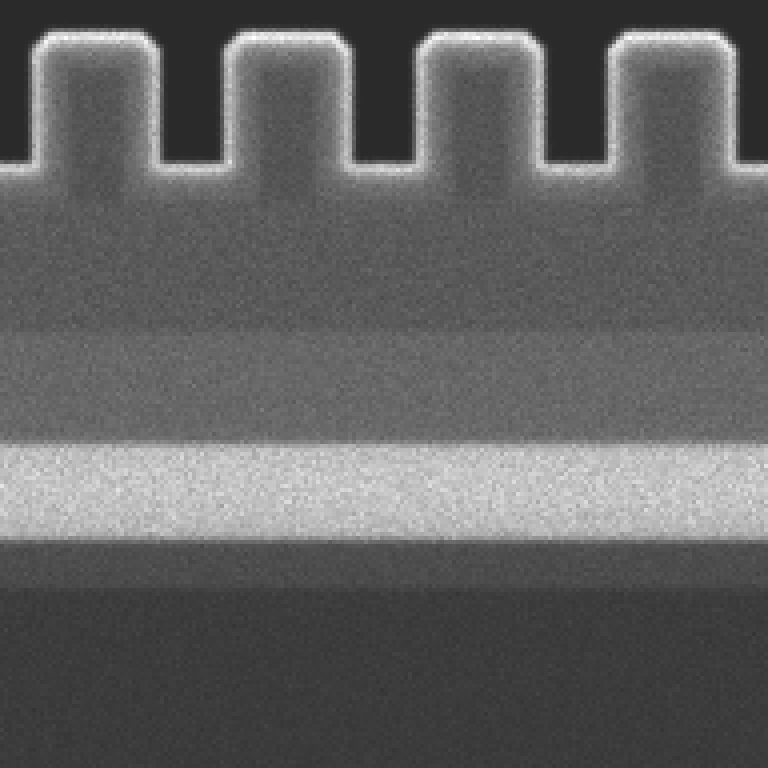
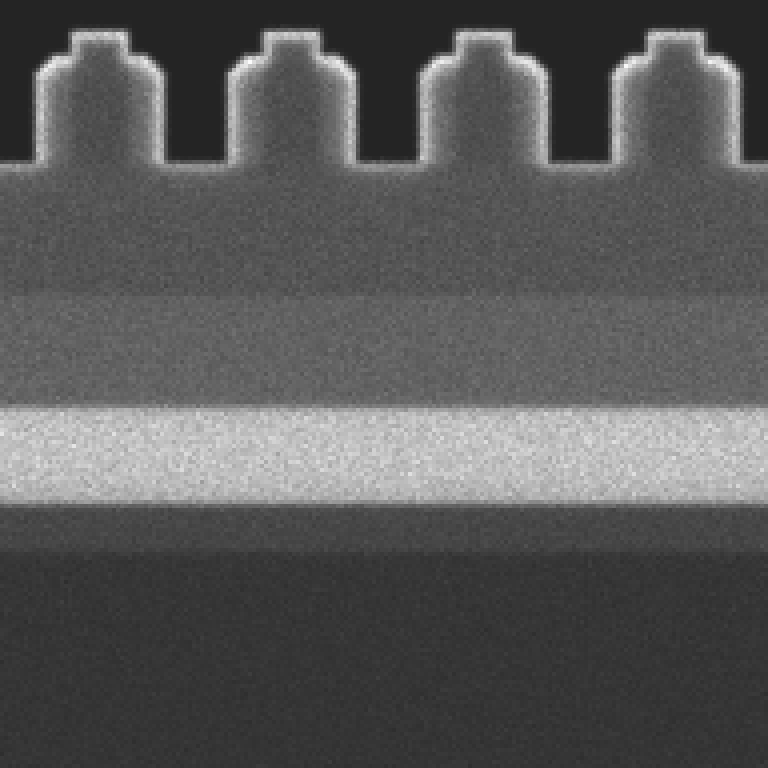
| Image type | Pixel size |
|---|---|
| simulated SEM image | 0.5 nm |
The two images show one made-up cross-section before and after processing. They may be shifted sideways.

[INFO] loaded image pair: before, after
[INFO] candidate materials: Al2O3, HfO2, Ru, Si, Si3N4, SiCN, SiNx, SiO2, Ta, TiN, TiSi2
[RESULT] removed SiO2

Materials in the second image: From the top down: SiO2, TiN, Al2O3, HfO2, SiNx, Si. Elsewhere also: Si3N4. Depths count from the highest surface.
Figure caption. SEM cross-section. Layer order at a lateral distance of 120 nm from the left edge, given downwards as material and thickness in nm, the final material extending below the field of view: empty 14, SiO2 52, TiN 66, Al2O3 56, HfO2 48, SiNx 24, Si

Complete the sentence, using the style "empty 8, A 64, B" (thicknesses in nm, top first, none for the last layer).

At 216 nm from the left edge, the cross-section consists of empty 14, SiO2 52, TiN 66, Al2O3 56, HfO2 48, SiNx 24, Si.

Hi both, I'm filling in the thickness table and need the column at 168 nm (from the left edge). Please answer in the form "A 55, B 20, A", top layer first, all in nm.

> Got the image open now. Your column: empty 12, SiO2 54, TiN 66, Al2O3 56, HfO2 48, SiNx 24, Si